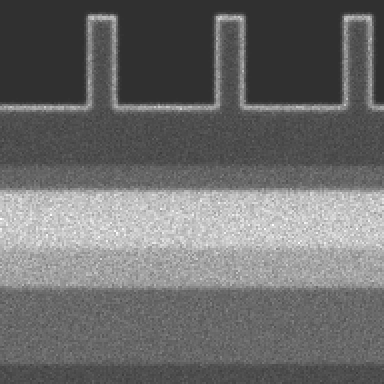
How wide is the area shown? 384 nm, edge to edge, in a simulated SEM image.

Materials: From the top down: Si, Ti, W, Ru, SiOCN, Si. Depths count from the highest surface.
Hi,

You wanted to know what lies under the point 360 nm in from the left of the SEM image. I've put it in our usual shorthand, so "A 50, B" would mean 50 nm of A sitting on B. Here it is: Si 150, Ti 24, W 58, Ru 40, SiOCN 76, Si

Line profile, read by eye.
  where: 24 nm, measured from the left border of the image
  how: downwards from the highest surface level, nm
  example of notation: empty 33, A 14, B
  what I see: empty 90, Si 60, Ti 24, W 58, Ru 40, SiOCN 76, Si